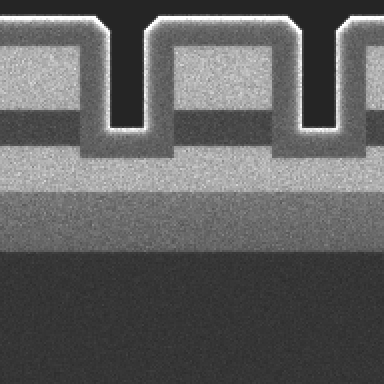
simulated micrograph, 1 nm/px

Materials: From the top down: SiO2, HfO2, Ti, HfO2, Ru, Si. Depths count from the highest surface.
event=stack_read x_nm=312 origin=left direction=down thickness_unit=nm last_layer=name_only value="empty 112, SiO2 30, HfO2 34, Ru 60, Si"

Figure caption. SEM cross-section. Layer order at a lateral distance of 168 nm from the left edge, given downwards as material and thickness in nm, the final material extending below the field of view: SiO2 142, HfO2 34, Ru 60, Si